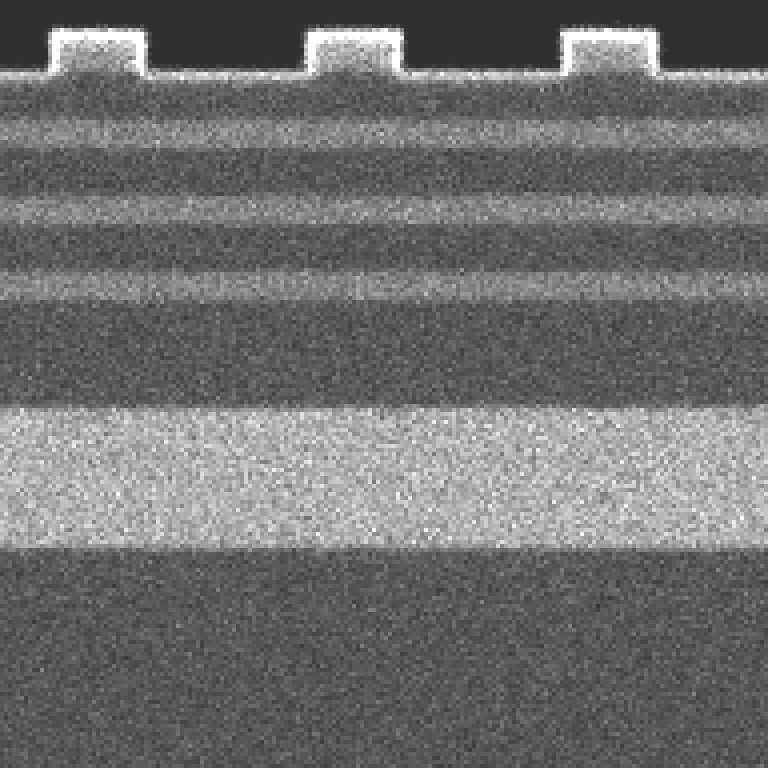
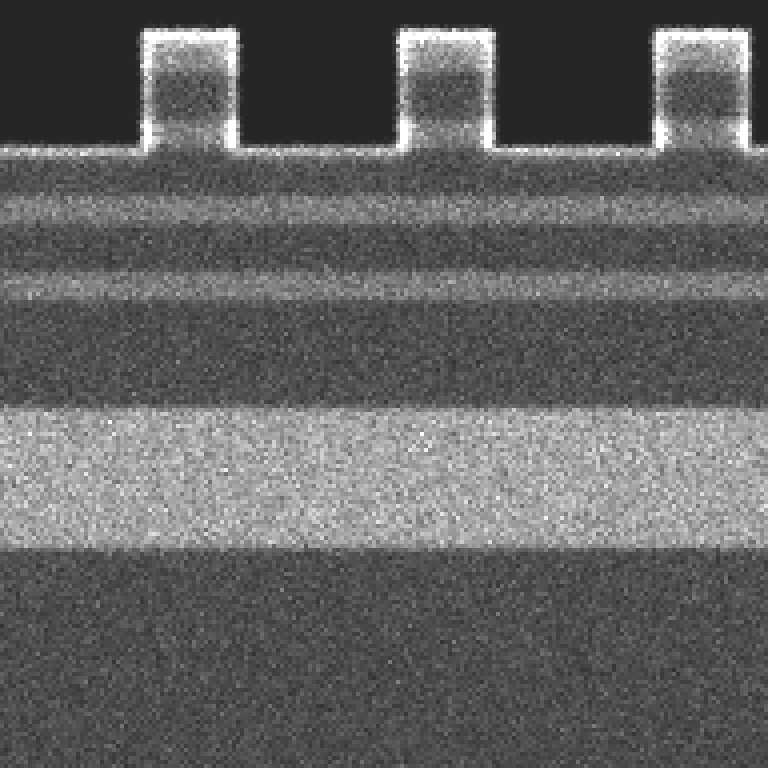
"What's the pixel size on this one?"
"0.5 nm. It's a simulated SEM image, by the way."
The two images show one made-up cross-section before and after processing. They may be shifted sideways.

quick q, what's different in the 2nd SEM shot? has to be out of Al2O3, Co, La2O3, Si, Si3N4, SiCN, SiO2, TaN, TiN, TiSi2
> Si and Si3N4 removed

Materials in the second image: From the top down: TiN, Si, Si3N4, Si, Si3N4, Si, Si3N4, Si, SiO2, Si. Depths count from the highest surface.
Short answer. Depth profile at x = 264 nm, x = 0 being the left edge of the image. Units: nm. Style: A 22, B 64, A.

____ empty 58, Si 24, Si3N4 14, Si 24, Si3N4 14, Si 54, SiO2 70, Si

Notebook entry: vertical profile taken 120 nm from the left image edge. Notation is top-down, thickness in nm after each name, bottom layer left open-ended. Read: empty 58, Si 24, Si3N4 14, Si 24, Si3N4 14, Si 54, SiO2 70, Si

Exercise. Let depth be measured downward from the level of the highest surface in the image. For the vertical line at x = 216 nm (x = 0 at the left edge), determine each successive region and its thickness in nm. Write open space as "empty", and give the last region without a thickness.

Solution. TiN 20, Si 24, Si3N4 14, Si 24, Si3N4 14, Si 24, Si3N4 14, Si 54, SiO2 70, Si